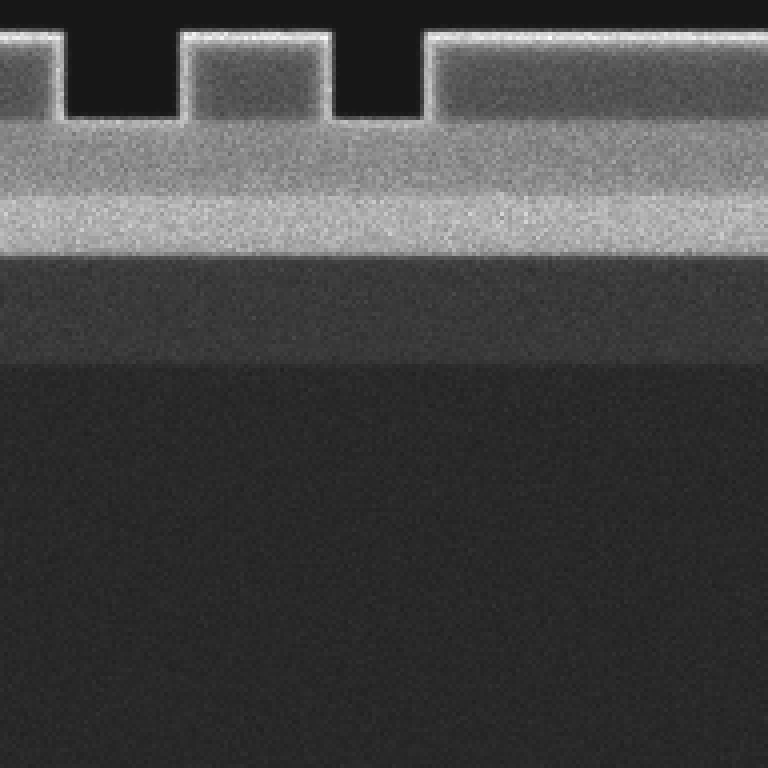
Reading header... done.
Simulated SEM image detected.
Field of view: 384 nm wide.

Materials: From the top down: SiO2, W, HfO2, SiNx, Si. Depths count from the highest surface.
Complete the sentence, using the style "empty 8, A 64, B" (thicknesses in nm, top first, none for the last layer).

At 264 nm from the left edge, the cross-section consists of SiO2 44, W 38, HfO2 30, SiNx 54, Si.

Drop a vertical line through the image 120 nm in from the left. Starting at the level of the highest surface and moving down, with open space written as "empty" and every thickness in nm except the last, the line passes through SiO2 44, W 38, HfO2 30, SiNx 54, Si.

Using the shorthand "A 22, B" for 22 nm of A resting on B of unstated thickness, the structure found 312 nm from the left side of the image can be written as SiO2 44, W 38, HfO2 30, SiNx 54, Si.